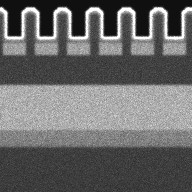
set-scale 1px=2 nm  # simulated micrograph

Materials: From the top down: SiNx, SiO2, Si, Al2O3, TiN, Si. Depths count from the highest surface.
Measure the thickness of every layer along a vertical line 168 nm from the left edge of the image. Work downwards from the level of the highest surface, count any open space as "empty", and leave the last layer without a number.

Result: empty 58, SiNx 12, SiO2 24, Si 60, Al2O3 90, TiN 34, Si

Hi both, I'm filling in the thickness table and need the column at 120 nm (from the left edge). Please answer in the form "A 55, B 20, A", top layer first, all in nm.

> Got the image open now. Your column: SiNx 12, Si 142, Al2O3 90, TiN 34, Si